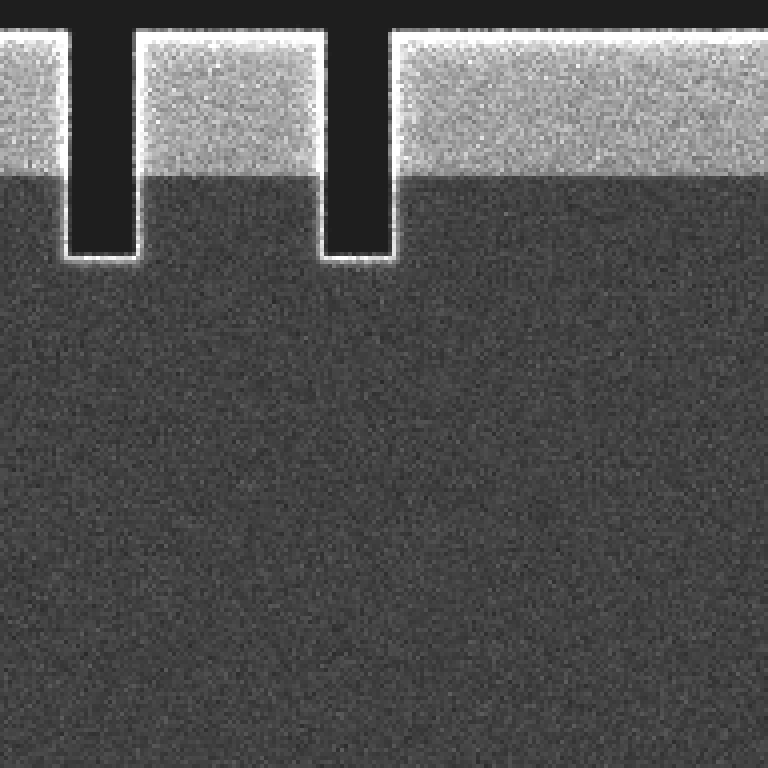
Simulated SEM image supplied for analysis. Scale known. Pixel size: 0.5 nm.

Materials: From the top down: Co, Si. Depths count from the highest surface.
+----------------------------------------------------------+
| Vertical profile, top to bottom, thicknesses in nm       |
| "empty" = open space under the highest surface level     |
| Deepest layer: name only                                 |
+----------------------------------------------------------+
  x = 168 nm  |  empty 112, Si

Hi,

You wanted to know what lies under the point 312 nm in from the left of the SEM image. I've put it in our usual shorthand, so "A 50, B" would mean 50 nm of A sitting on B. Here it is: Co 72, Si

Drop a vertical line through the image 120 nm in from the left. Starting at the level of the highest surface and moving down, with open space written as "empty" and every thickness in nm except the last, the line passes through Co 72, Si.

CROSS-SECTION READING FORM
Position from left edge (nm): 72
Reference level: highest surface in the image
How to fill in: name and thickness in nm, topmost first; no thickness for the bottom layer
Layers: Co 72, Si